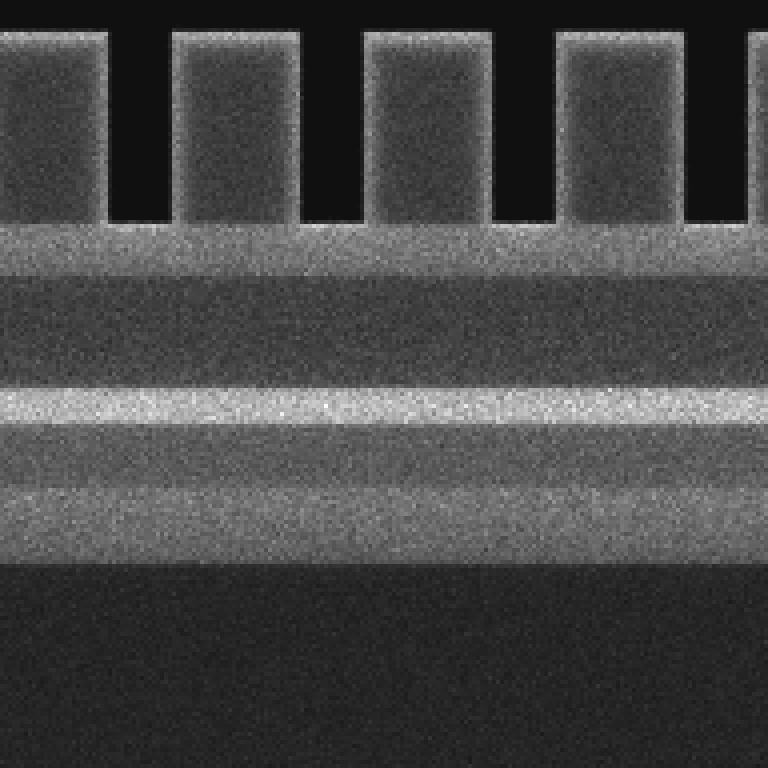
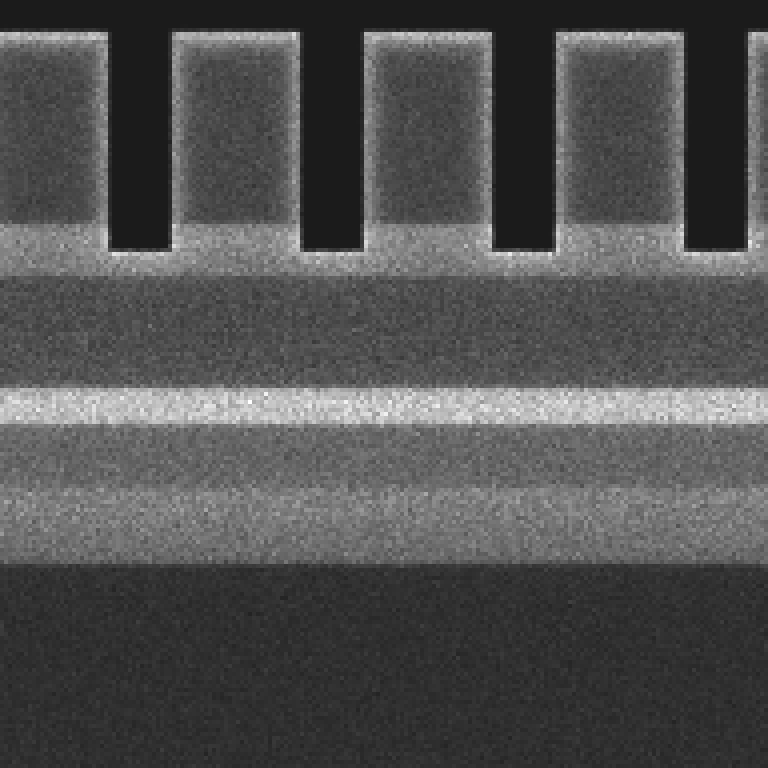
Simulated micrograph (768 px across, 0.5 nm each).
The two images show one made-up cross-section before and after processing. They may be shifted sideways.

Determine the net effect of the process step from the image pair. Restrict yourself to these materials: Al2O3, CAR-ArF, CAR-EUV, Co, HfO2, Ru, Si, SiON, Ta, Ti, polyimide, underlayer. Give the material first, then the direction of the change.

Ru: removed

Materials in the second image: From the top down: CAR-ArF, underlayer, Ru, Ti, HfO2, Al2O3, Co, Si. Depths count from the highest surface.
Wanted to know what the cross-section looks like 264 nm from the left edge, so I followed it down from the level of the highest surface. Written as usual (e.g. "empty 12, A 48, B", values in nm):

empty 110, Ru 12, Ti 56, HfO2 18, Al2O3 32, Co 38, Si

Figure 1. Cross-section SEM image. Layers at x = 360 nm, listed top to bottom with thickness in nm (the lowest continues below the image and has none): empty 110, Ru 12, Ti 56, HfO2 18, Al2O3 32, Co 38, Si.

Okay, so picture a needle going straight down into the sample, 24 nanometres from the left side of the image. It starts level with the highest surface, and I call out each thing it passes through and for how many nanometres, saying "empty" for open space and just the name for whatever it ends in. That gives CAR-ArF 60, underlayer 36, Ru 26, Ti 56, HfO2 18, Al2O3 32, Co 38, Si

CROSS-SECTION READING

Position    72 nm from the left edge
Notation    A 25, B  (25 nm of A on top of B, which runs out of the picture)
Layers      empty 110, Ru 12, Ti 56, HfO2 18, Al2O3 32, Co 38, Si